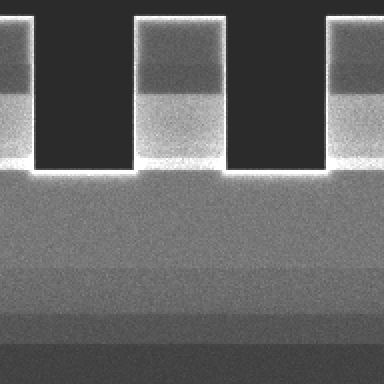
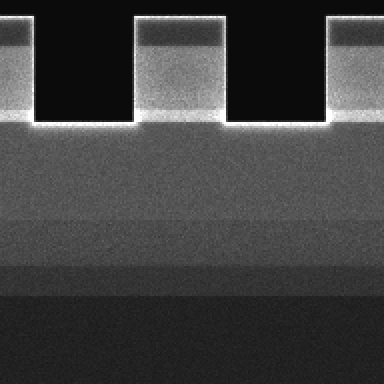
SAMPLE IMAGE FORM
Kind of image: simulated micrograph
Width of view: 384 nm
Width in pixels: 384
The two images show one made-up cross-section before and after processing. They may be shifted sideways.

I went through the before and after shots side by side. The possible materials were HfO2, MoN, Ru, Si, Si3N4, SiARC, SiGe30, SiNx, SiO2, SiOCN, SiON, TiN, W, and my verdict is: removed, SiARC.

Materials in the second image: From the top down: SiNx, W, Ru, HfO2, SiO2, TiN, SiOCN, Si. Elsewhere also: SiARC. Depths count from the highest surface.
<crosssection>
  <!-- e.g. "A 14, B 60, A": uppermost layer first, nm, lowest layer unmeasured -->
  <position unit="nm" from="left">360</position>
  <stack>SiNx 30, W 54, Ru 10, HfO2 12, SiO2 98, TiN 46, SiOCN 30, Si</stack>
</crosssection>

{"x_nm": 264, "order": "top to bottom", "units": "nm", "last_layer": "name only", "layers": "empty 106, SiO2 98, TiN 46, SiOCN 30, Si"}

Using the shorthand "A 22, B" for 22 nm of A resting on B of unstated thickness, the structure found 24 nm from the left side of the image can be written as SiNx 30, W 54, Ru 10, HfO2 12, SiO2 98, TiN 46, SiOCN 30, Si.